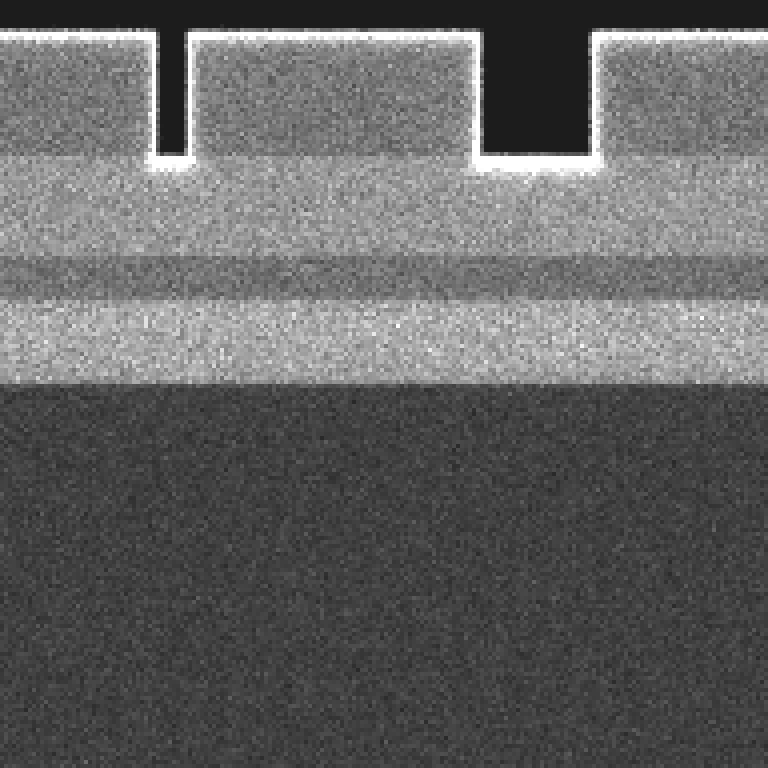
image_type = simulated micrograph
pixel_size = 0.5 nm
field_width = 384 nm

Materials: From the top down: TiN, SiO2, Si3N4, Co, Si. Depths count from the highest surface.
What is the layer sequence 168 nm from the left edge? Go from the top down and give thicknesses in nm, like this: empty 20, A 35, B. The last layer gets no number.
TiN 62, SiO2 50, Si3N4 22, Co 42, Si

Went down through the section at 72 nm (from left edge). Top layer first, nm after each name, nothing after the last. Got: TiN 62, SiO2 50, Si3N4 22, Co 42, Si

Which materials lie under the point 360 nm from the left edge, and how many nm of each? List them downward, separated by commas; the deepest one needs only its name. TiN 62, SiO2 50, Si3N4 22, Co 42, Si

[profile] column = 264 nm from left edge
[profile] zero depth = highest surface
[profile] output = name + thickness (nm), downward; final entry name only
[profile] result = empty 62, SiO2 50, Si3N4 22, Co 42, Si